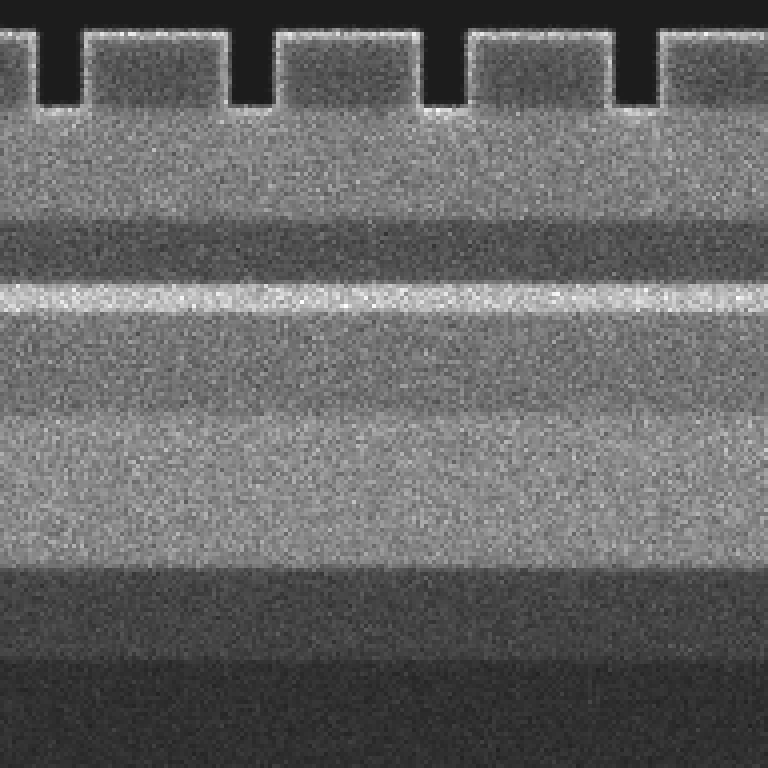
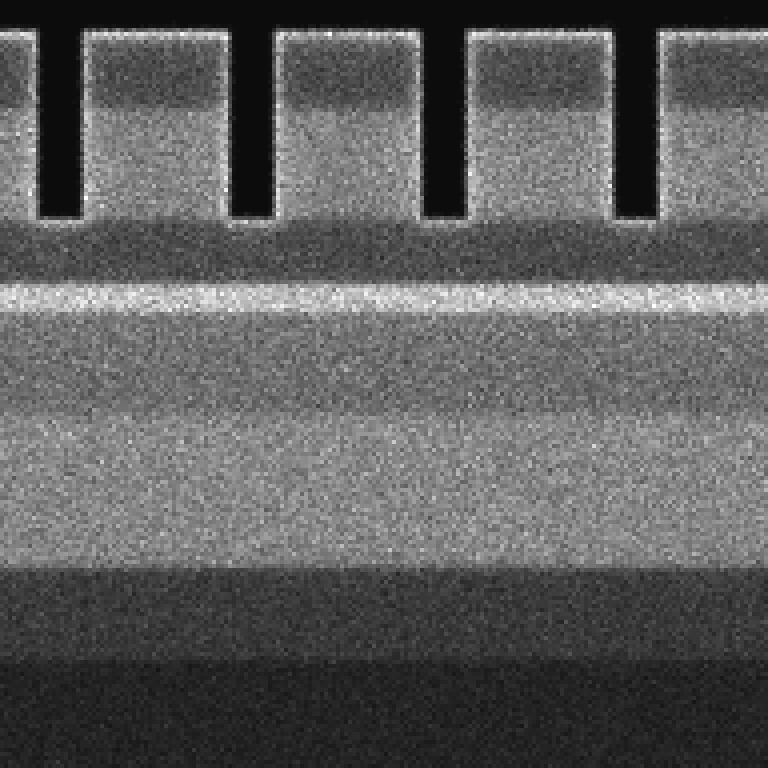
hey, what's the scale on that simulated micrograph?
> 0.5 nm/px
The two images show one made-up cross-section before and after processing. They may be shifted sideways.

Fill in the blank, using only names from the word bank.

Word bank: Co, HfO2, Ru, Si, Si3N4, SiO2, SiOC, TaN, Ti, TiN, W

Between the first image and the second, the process removed Ru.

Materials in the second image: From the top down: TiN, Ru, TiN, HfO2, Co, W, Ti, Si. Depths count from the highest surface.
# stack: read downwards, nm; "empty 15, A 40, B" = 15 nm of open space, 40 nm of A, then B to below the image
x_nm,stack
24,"empty 94, TiN 32, HfO2 14, Co 52, W 76, Ti 46, Si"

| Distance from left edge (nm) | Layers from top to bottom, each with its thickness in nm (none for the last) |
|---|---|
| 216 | empty 94, TiN 32, HfO2 14, Co 52, W 76, Ti 46, Si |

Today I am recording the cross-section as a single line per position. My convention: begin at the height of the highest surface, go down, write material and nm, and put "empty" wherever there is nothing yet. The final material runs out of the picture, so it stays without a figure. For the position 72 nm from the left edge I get TiN 38, Ru 56, TiN 32, HfO2 14, Co 52, W 76, Ti 46, Si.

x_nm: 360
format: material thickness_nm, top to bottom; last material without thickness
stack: TiN 38, Ru 56, TiN 32, HfO2 14, Co 52, W 76, Ti 46, Si